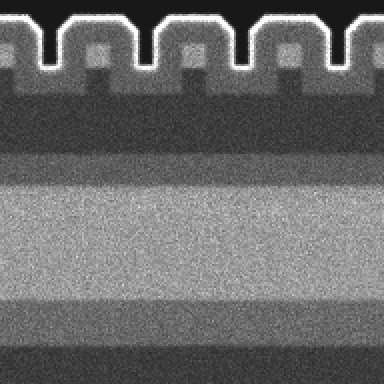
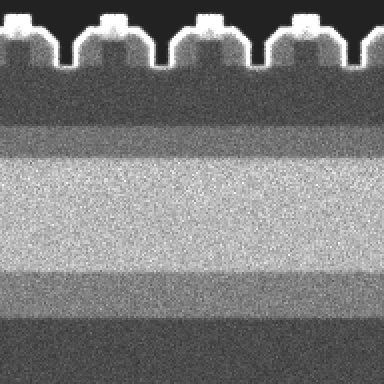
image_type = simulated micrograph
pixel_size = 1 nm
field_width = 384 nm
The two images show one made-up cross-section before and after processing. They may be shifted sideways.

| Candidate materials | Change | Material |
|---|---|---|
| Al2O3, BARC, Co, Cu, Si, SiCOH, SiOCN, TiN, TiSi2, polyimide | removed | SiOCN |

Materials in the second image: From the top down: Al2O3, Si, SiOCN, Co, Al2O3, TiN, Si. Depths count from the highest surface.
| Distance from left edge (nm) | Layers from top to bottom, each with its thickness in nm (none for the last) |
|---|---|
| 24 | Al2O3 24, Si 86, SiOCN 32, Co 36, Al2O3 78, TiN 46, Si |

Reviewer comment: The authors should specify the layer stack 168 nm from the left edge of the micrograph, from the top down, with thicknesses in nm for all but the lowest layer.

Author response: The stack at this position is empty 50, Si 60, SiOCN 32, Co 36, Al2O3 78, TiN 46, Si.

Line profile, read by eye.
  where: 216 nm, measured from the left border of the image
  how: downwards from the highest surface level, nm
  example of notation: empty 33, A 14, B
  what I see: Al2O3 24, Si 86, SiOCN 32, Co 36, Al2O3 78, TiN 46, Si